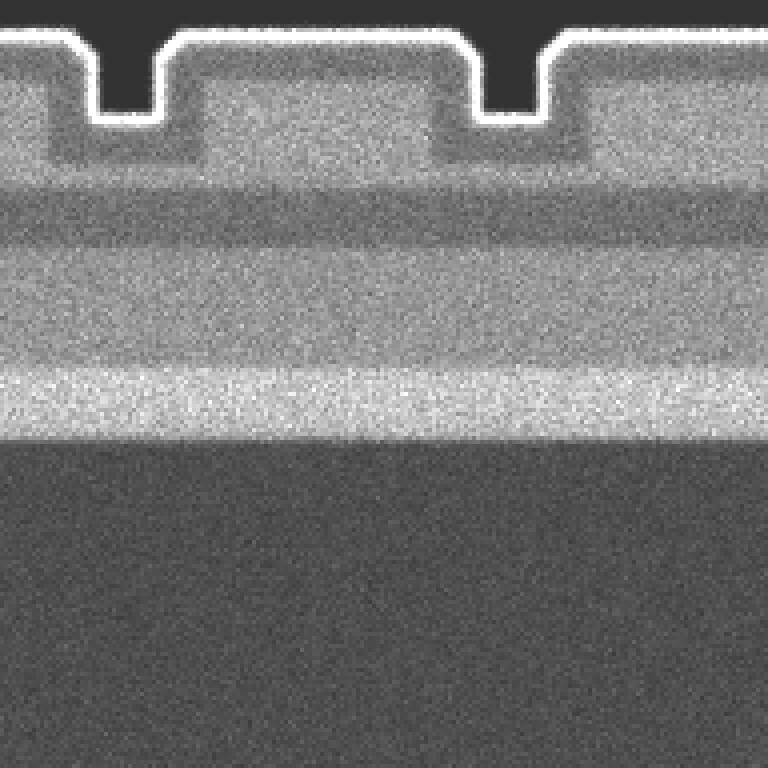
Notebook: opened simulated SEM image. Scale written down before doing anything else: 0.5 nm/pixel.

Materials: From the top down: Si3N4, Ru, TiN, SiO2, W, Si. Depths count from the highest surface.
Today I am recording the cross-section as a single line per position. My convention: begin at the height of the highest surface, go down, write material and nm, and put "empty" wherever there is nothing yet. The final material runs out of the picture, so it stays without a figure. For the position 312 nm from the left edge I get Si3N4 24, Ru 54, TiN 30, SiO2 60, W 36, Si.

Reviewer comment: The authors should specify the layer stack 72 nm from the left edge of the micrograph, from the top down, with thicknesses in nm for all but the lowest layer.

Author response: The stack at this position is empty 42, Si3N4 24, Ru 12, TiN 30, SiO2 60, W 36, Si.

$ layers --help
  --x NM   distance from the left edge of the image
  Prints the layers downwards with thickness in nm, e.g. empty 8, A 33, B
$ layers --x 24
Si3N4 66, Ru 12, TiN 30, SiO2 60, W 36, Si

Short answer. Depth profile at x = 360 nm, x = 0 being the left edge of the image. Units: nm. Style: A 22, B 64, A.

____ Si3N4 24, Ru 54, TiN 30, SiO2 60, W 36, Si